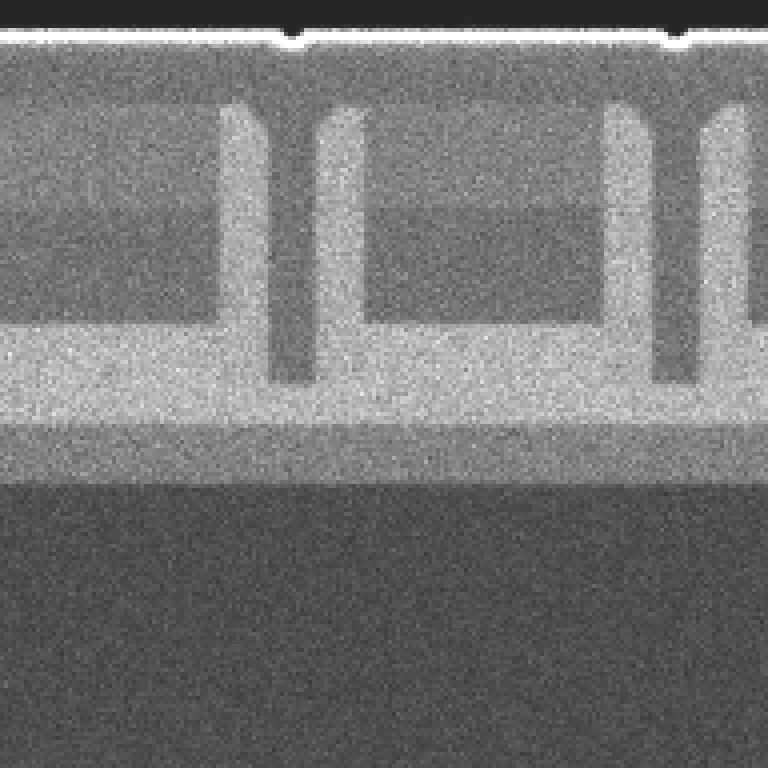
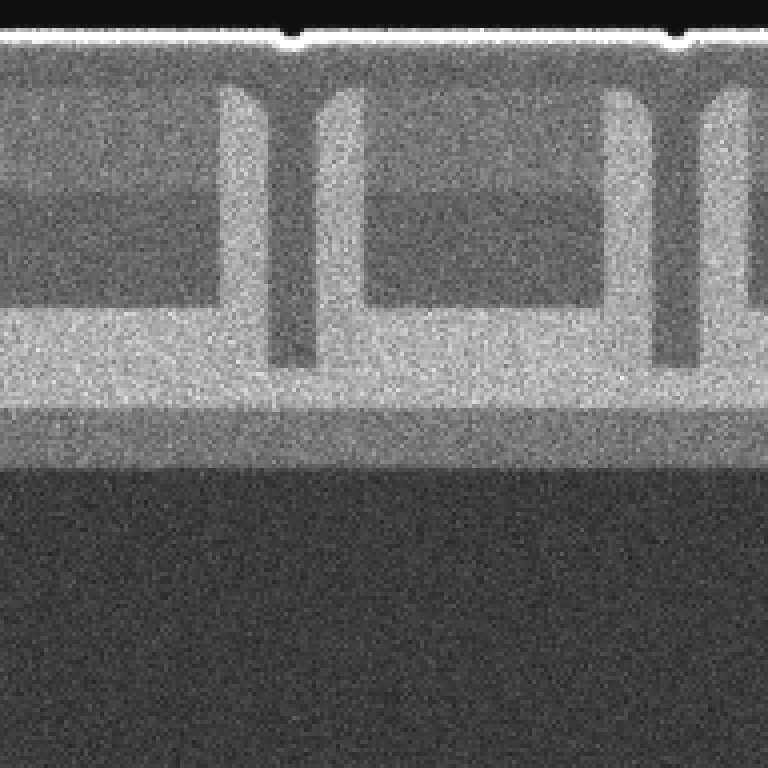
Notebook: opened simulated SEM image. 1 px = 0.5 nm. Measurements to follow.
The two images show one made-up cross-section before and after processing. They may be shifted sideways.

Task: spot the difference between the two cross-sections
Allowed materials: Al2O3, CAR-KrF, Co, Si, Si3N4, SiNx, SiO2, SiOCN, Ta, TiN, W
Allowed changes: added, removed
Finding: removed SiNx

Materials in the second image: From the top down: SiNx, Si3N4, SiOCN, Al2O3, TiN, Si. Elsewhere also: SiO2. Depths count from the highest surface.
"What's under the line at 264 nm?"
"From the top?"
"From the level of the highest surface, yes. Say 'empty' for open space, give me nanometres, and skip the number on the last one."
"SiNx 28, Si3N4 52, SiOCN 58, Al2O3 50, TiN 30, Si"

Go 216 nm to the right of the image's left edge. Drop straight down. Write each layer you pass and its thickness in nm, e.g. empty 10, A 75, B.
SiNx 28, Si3N4 52, SiOCN 58, Al2O3 50, TiN 30, Si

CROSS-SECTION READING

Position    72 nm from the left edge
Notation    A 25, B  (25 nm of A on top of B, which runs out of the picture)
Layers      SiNx 28, Si3N4 52, SiOCN 58, Al2O3 50, TiN 30, Si